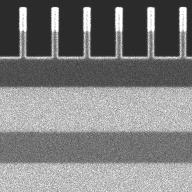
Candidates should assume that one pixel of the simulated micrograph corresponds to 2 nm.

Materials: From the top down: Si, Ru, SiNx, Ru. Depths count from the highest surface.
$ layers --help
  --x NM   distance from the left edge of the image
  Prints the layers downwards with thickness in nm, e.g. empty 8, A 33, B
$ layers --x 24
empty 98, Si 60, Ru 90, SiNx 62, Ru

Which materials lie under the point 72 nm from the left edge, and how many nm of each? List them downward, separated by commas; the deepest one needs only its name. empty 98, Si 60, Ru 90, SiNx 62, Ru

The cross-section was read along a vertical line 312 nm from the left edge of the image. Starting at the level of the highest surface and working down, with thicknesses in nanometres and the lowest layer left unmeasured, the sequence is empty 98, Si 60, Ru 90, SiNx 62, Ru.